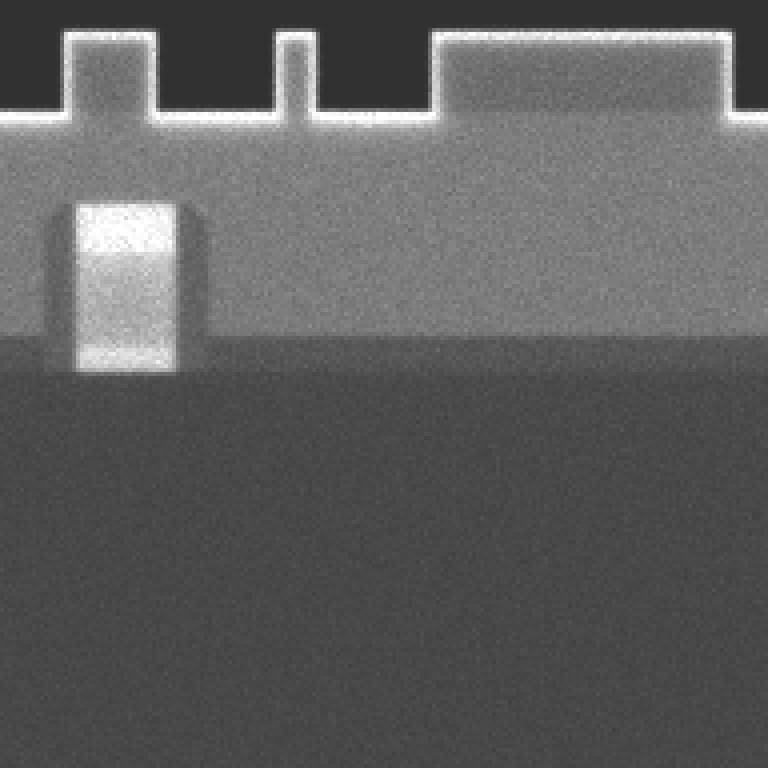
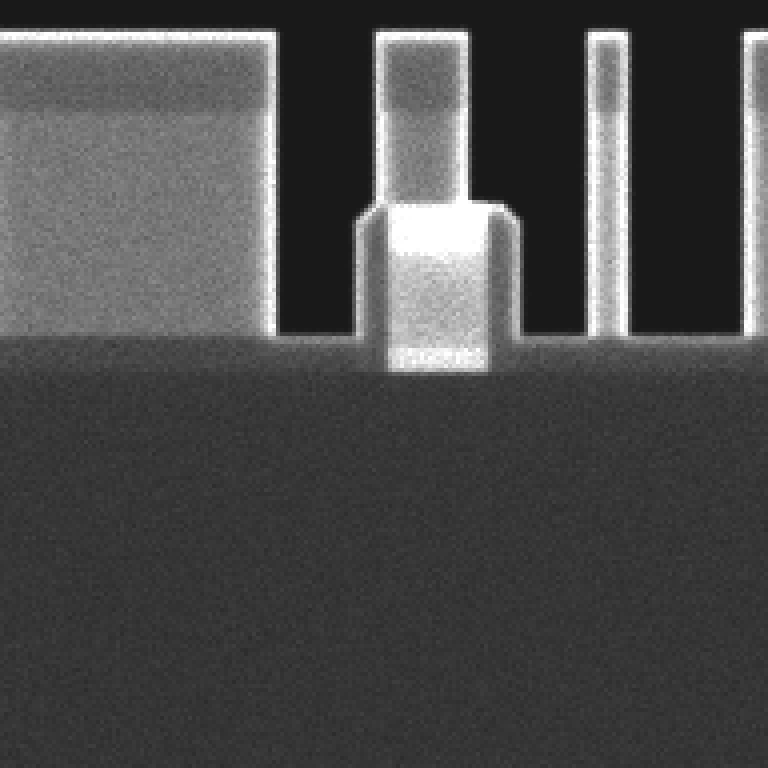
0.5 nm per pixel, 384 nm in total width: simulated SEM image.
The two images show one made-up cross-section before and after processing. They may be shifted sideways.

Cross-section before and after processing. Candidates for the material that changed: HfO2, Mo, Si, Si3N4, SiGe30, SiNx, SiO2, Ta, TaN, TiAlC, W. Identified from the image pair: SiO2 (removed).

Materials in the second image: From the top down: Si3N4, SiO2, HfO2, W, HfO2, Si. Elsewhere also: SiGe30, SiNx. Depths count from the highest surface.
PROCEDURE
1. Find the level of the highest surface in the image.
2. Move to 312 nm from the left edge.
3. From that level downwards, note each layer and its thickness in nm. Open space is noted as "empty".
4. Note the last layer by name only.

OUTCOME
Si3N4 40, SiO2 112, SiGe30 18, Si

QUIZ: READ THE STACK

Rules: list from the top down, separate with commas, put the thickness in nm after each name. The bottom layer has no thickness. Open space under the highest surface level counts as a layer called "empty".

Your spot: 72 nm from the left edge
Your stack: Si3N4 40, SiO2 112, SiGe30 18, Si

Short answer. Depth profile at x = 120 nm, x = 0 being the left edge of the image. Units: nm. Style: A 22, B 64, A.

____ Si3N4 40, SiO2 112, SiGe30 18, Si